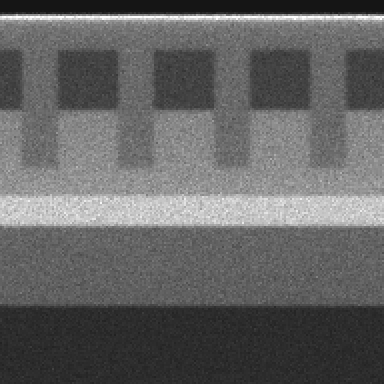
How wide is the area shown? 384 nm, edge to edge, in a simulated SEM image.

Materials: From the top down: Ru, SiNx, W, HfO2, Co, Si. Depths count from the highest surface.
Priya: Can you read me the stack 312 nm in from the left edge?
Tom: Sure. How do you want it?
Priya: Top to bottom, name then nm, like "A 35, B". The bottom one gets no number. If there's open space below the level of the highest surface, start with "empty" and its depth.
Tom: Ru 152, W 28, HfO2 30, Co 80, Si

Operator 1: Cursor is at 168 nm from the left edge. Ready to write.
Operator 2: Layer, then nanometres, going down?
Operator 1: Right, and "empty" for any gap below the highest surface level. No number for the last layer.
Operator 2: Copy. Ru 34, SiNx 60, W 86, HfO2 30, Co 80, Si